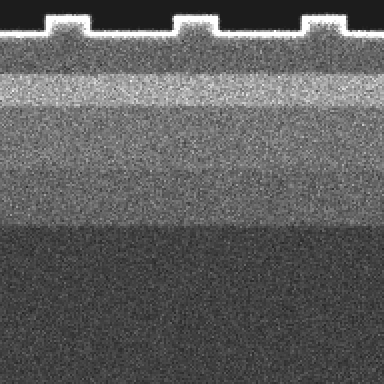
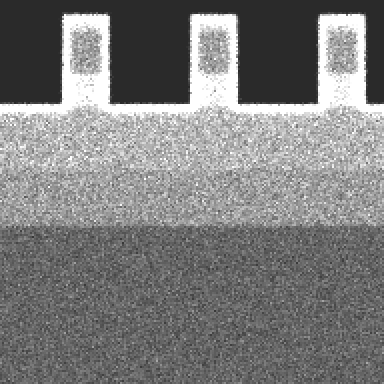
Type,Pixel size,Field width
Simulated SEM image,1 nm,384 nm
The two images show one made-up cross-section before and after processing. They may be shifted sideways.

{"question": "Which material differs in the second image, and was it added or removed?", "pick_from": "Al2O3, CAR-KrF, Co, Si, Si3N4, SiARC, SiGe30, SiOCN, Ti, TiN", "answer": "Al2O3 and SiOCN, removed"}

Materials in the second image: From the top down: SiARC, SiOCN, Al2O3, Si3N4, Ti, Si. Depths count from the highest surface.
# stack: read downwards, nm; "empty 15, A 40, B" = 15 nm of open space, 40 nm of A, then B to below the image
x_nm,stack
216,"SiARC 16, SiOCN 42, Al2O3 32, Si3N4 64, Ti 56, Si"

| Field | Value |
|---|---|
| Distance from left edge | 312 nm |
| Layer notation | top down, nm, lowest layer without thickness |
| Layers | empty 90, Si3N4 64, Ti 56, Si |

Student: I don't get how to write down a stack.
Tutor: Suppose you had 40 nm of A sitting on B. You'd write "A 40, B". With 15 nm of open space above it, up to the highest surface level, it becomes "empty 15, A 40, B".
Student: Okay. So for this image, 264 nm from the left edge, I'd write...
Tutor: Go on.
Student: empty 90, Si3N4 64, Ti 56, Si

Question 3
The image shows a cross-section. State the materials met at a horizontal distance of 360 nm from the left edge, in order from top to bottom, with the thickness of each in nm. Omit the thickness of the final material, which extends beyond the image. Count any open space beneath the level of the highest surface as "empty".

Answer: SiARC 16, SiOCN 42, Al2O3 32, Si3N4 64, Ti 56, Si